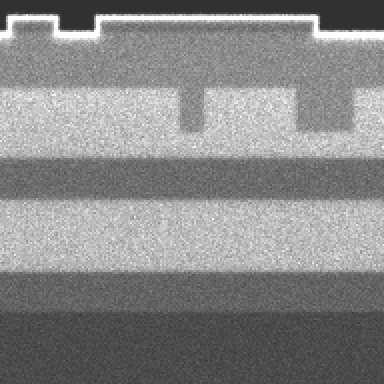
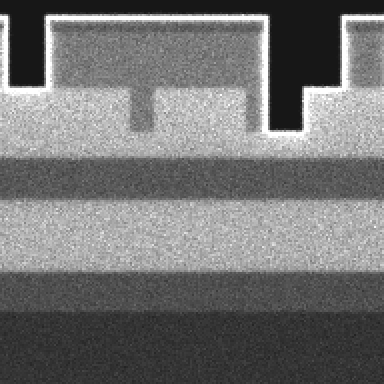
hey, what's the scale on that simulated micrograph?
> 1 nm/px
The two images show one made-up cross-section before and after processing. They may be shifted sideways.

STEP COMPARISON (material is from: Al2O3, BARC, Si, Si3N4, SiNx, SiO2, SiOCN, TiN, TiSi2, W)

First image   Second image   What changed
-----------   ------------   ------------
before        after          SiO2, removed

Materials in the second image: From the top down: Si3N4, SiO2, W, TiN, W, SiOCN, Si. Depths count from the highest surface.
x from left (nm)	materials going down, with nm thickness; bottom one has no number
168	Si3N4 16, SiO2 56, W 70, TiN 42, W 72, SiOCN 40, Si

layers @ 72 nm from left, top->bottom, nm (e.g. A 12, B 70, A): Si3N4 16, SiO2 56, W 70, TiN 42, W 72, SiOCN 40, Si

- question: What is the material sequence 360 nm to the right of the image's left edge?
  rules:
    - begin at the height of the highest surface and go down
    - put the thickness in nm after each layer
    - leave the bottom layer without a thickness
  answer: Si3N4 16, SiO2 56, W 70, TiN 42, W 72, SiOCN 40, Si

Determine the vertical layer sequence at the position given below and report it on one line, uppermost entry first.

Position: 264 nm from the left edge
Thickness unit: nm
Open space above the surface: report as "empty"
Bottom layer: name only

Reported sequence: Si3N4 16, SiO2 100, W 26, TiN 42, W 72, SiOCN 40, Si